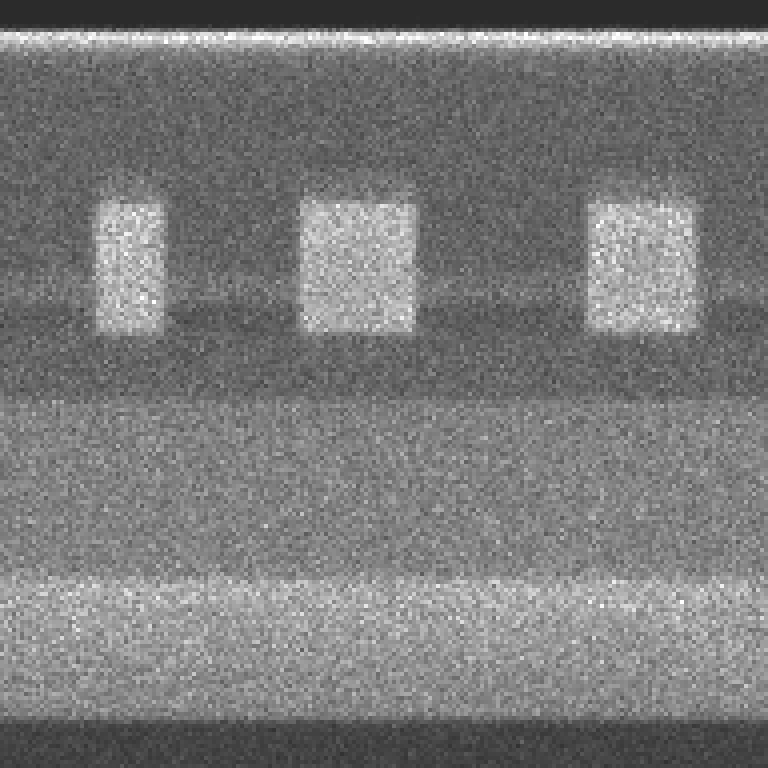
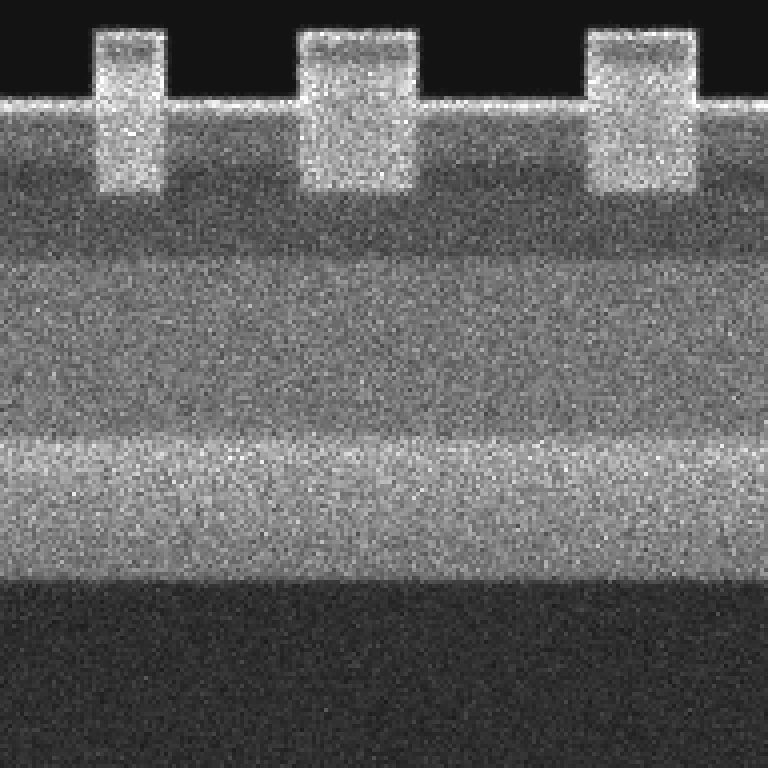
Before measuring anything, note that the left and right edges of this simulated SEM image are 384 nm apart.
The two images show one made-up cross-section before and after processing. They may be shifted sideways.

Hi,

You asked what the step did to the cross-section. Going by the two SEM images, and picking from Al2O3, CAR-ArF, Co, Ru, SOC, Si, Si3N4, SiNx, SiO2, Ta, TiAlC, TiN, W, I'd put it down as SOC, removed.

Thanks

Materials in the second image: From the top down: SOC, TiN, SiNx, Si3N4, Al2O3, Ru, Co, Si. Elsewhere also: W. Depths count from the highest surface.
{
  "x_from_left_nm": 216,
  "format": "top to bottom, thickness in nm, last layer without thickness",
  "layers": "empty 34, SOC 16, TiN 16, SiNx 14, Si3N4 34, Al2O3 90, Ru 44, Co 26, Si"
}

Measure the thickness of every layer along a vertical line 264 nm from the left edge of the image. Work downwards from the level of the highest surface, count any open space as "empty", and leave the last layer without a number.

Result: empty 34, SOC 16, TiN 16, SiNx 14, Si3N4 34, Al2O3 90, Ru 44, Co 26, Si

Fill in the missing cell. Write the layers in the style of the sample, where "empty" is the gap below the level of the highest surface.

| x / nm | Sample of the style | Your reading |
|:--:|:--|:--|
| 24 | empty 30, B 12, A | empty 34, SOC 16, TiN 16, SiNx 14, Si3N4 34, Al2O3 90, Ru 44, Co 26, Si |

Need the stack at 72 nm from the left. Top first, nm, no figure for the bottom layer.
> TiN 16, W 64, Si3N4 34, Al2O3 90, Ru 44, Co 26, Si